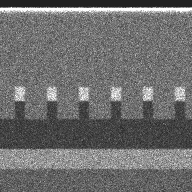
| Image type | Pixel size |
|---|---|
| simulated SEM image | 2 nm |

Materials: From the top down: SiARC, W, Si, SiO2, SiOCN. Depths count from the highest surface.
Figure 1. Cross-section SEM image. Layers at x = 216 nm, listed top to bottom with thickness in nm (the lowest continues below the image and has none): SiARC 222, Si 60, SiO2 40, SiOCN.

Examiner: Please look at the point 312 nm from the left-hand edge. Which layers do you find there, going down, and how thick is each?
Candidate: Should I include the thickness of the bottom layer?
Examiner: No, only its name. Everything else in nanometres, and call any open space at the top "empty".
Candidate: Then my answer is SiARC 222, Si 60, SiO2 40, SiOCN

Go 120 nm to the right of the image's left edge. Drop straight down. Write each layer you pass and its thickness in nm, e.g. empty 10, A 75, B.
SiARC 222, Si 60, SiO2 40, SiOCN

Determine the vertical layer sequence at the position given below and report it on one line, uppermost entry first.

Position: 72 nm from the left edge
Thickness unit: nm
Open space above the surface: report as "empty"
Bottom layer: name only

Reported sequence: SiARC 222, Si 60, SiO2 40, SiOCN